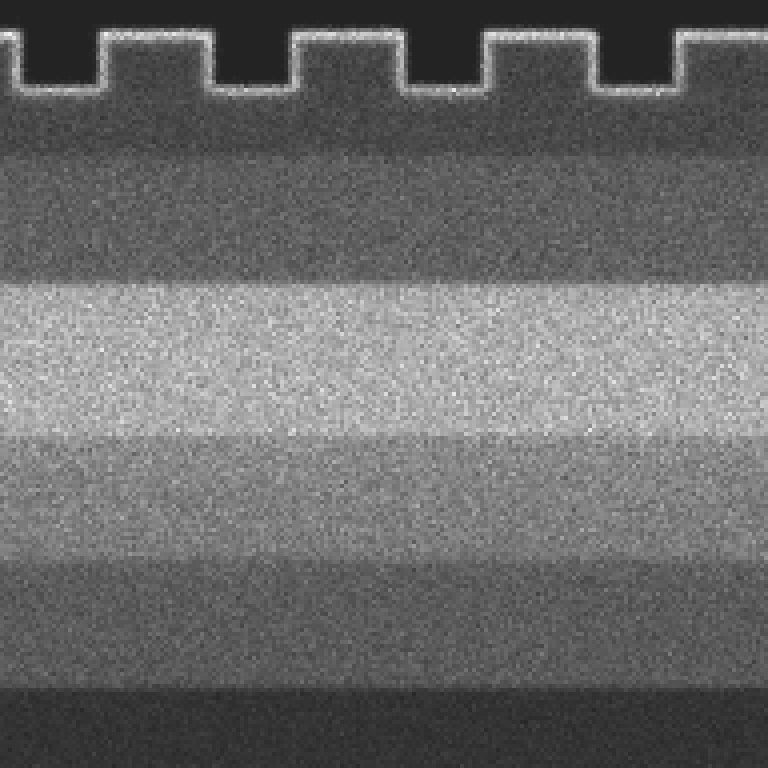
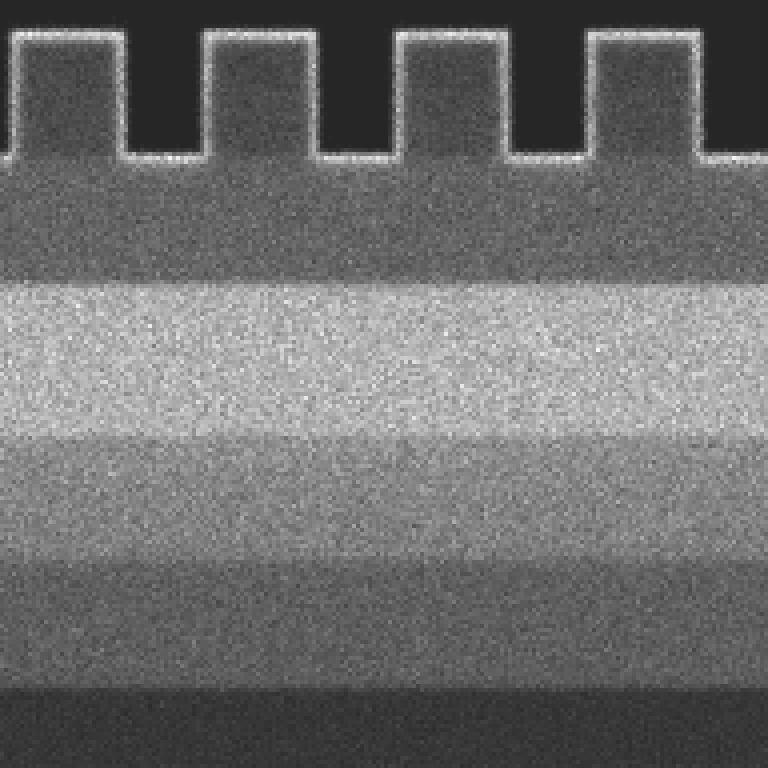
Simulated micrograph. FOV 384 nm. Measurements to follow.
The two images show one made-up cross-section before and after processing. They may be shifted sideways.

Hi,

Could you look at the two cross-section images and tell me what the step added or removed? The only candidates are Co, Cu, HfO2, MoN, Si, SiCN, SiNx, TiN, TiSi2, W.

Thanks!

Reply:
removed TiN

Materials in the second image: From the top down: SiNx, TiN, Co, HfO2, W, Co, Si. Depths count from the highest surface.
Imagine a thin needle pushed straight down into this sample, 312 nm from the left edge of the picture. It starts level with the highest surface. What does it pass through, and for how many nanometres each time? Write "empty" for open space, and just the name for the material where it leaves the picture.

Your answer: SiNx 28, TiN 34, Co 64, HfO2 76, W 62, Co 64, Si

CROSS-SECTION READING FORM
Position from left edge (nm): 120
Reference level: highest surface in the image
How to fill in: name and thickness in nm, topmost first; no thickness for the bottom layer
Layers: SiNx 28, TiN 34, Co 64, HfO2 76, W 62, Co 64, Si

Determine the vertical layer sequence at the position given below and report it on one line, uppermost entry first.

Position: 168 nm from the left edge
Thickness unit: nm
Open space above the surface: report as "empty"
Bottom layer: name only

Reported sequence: empty 62, Co 64, HfO2 76, W 62, Co 64, Si